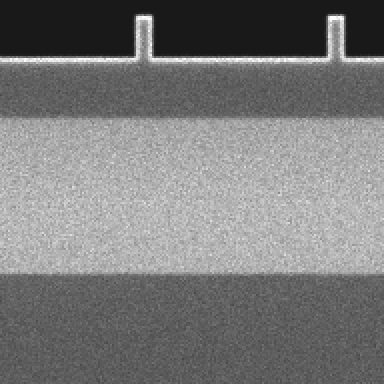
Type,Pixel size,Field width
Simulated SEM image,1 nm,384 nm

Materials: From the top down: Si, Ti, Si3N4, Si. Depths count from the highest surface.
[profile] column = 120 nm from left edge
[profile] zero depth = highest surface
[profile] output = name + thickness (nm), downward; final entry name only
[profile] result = empty 42, Si 60, Ti 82, Si3N4 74, Si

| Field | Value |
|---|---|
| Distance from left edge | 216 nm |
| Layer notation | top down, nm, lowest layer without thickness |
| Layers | empty 42, Si 60, Ti 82, Si3N4 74, Si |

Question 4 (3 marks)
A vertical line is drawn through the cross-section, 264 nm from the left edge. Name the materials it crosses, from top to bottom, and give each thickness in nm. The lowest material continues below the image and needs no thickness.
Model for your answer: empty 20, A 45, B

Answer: empty 42, Si 60, Ti 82, Si3N4 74, Si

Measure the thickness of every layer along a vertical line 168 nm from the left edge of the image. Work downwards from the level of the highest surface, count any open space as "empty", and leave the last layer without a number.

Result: empty 42, Si 60, Ti 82, Si3N4 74, Si